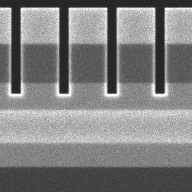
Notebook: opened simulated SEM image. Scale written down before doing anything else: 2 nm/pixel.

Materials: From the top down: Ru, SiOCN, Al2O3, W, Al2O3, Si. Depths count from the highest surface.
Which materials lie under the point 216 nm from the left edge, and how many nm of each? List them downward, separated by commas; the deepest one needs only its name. empty 172, Al2O3 32, W 66, Al2O3 48, Si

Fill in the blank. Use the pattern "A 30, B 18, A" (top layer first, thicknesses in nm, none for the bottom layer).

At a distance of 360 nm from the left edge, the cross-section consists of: Ru 72, SiOCN 78, Al2O3 54, W 66, Al2O3 48, Si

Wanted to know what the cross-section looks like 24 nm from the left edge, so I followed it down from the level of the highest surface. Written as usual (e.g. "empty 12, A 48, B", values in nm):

empty 172, Al2O3 32, W 66, Al2O3 48, Si